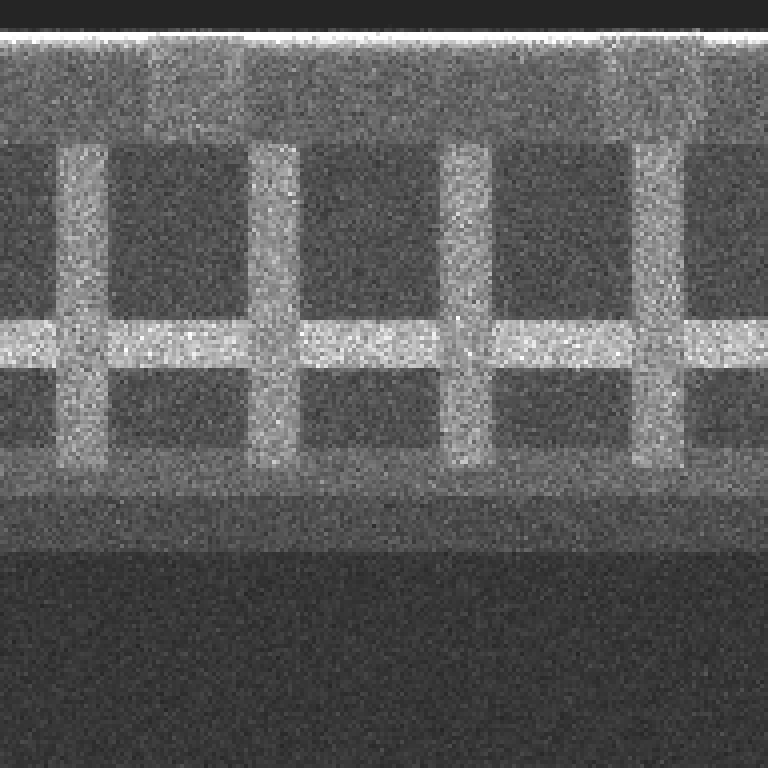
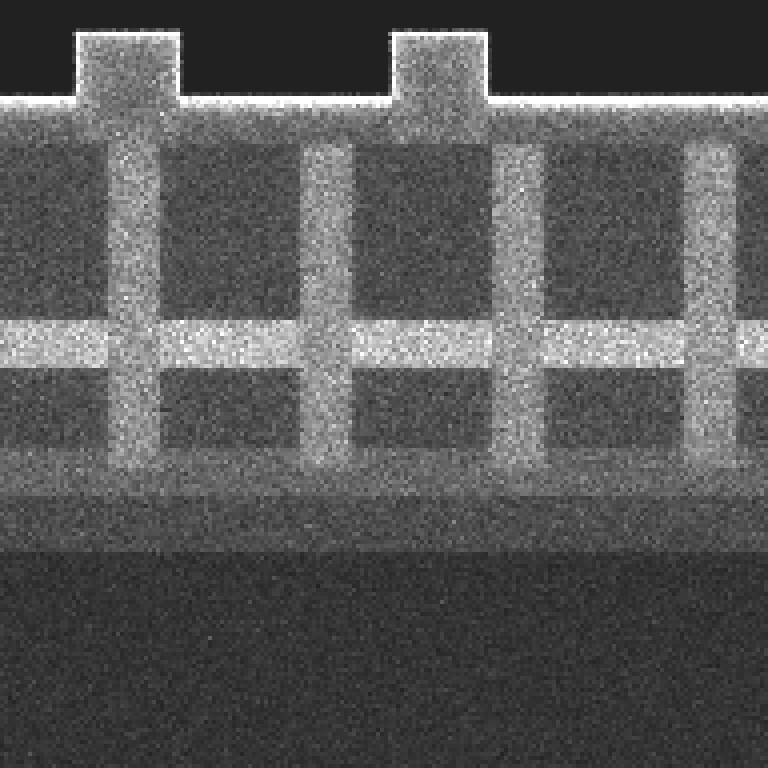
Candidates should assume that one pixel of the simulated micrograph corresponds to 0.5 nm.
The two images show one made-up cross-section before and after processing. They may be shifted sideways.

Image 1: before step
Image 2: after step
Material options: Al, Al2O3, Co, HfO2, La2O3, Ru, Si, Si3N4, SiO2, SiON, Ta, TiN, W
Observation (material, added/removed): SiO2, removed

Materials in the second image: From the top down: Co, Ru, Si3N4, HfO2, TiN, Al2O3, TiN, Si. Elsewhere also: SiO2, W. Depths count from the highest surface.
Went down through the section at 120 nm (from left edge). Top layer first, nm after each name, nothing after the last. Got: empty 32, SiO2 24, Si3N4 88, HfO2 24, TiN 40, Al2O3 24, TiN 28, Si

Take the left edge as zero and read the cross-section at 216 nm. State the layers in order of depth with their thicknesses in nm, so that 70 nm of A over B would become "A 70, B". Co 46, Ru 10, Si3N4 88, HfO2 24, TiN 40, Al2O3 24, TiN 28, Si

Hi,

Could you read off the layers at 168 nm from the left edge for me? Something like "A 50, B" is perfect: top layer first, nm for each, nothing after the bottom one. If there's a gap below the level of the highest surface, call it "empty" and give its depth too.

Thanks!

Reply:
empty 32, SiO2 24, W 162, Al2O3 14, TiN 28, Si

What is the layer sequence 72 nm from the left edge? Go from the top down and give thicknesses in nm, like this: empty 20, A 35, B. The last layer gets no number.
Co 46, Ru 10, W 162, Al2O3 14, TiN 28, Si